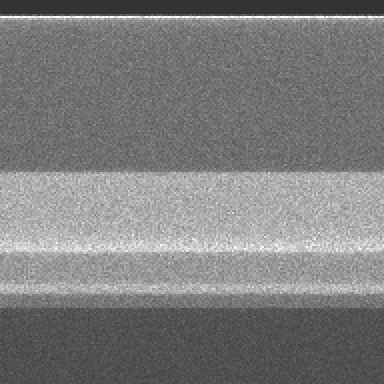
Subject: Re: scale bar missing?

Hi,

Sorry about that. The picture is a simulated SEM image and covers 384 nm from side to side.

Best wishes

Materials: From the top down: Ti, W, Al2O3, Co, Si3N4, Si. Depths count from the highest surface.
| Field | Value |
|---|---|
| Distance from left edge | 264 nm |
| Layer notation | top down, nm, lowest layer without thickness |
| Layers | Ti 156, W 80, Al2O3 32, Co 10, Si3N4 14, Si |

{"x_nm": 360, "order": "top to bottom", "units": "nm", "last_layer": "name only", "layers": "Ti 156, W 80, Al2O3 32, Co 10, Si3N4 14, Si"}